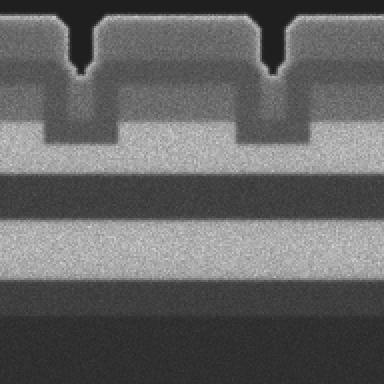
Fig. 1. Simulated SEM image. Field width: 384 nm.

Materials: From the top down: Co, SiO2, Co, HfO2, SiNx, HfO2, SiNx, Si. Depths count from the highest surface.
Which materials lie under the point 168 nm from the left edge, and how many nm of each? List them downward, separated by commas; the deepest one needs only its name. Co 44, SiO2 24, Co 38, HfO2 52, SiNx 46, HfO2 60, SiNx 36, Si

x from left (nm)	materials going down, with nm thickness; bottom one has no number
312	Co 44, SiO2 24, Co 38, HfO2 52, SiNx 46, HfO2 60, SiNx 36, Si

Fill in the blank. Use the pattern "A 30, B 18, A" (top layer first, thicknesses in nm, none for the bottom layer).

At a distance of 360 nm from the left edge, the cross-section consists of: Co 44, SiO2 24, Co 38, HfO2 52, SiNx 46, HfO2 60, SiNx 36, Si